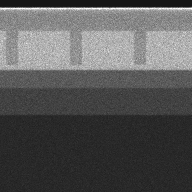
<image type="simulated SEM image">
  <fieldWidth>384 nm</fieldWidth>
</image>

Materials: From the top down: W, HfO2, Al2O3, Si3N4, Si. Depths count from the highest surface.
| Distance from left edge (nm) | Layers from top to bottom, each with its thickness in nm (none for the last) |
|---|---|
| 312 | W 46, HfO2 78, Al2O3 36, Si3N4 54, Si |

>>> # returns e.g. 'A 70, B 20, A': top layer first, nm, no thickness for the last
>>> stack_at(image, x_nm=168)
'W 46, HfO2 78, Al2O3 36, Si3N4 54, Si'